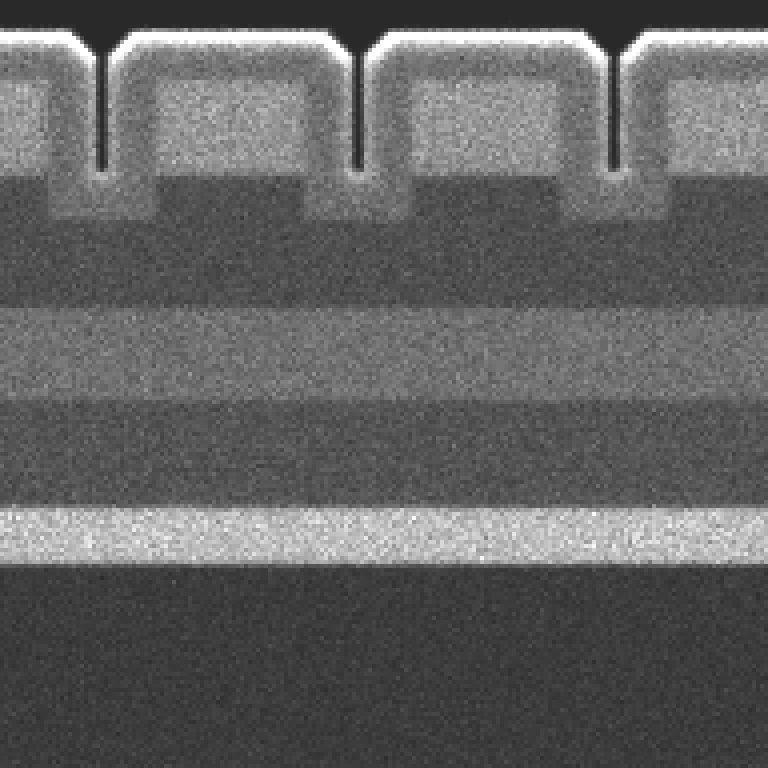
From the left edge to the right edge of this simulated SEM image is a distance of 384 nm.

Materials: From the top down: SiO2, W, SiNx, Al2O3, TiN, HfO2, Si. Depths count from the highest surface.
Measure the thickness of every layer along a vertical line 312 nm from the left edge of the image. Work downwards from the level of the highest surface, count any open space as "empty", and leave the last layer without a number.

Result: empty 10, SiO2 84, SiNx 44, Al2O3 46, TiN 54, HfO2 28, Si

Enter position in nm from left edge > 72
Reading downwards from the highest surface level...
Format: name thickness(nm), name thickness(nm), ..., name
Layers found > SiO2 94, SiNx 44, Al2O3 46, TiN 54, HfO2 28, Si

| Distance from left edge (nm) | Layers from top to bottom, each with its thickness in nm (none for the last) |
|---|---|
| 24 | SiO2 94, SiNx 44, Al2O3 46, TiN 54, HfO2 28, Si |